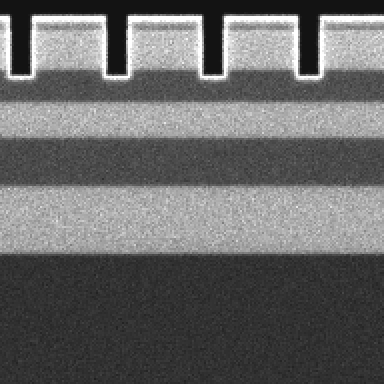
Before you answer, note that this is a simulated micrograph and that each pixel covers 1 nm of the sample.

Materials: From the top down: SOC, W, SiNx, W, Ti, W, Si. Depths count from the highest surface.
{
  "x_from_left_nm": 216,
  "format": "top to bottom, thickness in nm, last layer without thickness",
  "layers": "empty 60, SiNx 26, W 36, Ti 48, W 68, Si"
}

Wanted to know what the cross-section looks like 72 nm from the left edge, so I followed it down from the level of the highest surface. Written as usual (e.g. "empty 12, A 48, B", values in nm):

SOC 14, W 40, SiNx 32, W 36, Ti 48, W 68, Si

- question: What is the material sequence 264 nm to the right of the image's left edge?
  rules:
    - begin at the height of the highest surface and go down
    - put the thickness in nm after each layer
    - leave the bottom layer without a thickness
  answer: SOC 14, W 40, SiNx 32, W 36, Ti 48, W 68, Si